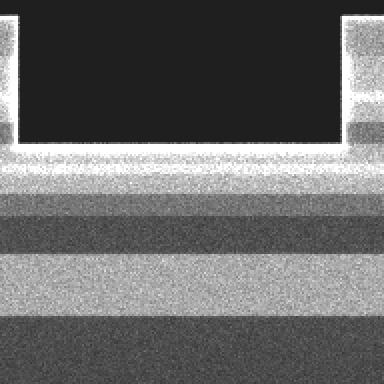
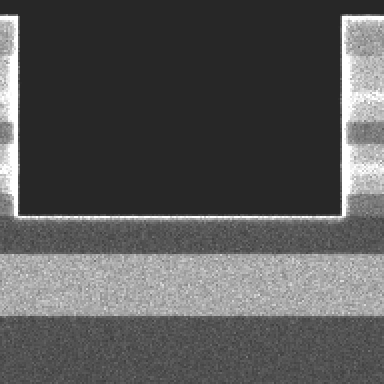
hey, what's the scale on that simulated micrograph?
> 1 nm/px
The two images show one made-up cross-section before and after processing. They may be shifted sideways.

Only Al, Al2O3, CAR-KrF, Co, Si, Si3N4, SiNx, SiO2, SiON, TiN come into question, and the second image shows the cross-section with Al2O3 and Co and SiNx removed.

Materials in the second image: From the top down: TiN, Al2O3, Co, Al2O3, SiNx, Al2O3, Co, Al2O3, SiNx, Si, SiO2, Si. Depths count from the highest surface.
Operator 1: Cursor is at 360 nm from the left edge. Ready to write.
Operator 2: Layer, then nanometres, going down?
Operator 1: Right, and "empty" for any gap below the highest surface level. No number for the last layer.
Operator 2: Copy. TiN 40, Al2O3 36, Co 10, Al2O3 20, SiNx 22, Al2O3 20, Co 10, Al2O3 20, SiNx 22, Si 38, SiO2 62, Si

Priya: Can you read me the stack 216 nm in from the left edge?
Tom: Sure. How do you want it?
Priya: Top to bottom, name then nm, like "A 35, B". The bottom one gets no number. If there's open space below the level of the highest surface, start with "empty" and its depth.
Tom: empty 200, Si 38, SiO2 62, Si